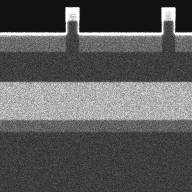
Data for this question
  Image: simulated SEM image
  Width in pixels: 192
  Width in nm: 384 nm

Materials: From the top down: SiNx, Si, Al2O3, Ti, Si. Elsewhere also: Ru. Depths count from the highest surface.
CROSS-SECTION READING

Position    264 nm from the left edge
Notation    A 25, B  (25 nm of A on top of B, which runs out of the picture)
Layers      empty 50, SiNx 38, Si 60, Al2O3 76, Ti 24, Si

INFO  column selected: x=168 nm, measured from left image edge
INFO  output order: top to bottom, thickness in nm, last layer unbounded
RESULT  empty 50, SiNx 38, Si 60, Al2O3 76, Ti 24, Si